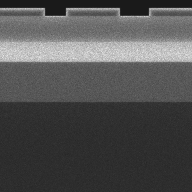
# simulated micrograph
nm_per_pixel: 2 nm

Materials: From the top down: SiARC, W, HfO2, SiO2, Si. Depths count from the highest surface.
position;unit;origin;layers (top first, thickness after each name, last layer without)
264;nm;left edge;empty 16, W 52, HfO2 40, SiO2 80, Si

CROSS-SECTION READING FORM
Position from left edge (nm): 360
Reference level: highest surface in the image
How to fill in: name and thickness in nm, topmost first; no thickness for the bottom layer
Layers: SiARC 16, W 52, HfO2 40, SiO2 80, Si